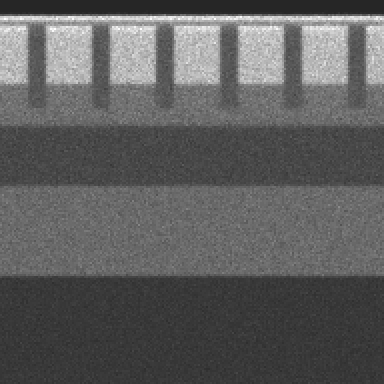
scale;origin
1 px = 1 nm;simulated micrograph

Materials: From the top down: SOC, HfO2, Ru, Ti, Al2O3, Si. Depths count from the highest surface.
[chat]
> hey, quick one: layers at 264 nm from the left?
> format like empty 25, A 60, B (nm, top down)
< SOC 10, HfO2 58, Ru 42, Ti 60, Al2O3 90, Si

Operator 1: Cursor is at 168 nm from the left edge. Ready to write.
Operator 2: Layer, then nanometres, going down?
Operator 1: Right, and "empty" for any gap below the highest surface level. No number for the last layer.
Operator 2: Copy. SOC 92, Ru 18, Ti 60, Al2O3 90, Si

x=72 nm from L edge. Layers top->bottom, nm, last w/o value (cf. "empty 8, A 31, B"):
SOC 10, HfO2 58, Ru 42, Ti 60, Al2O3 90, Si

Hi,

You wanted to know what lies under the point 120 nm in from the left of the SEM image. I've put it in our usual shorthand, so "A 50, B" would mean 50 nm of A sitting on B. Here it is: SOC 10, HfO2 58, Ru 42, Ti 60, Al2O3 90, Si